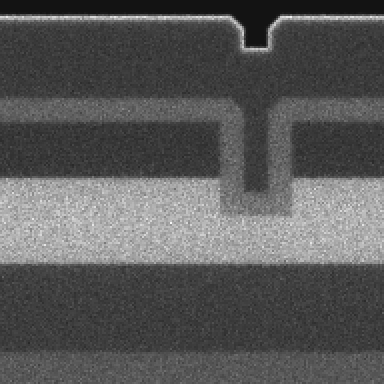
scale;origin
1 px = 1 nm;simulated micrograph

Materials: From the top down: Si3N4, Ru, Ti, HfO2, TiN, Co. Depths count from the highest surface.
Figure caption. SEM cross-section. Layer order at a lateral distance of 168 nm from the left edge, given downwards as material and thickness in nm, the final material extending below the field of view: Si3N4 82, Ru 24, Ti 56, HfO2 86, TiN 88, Co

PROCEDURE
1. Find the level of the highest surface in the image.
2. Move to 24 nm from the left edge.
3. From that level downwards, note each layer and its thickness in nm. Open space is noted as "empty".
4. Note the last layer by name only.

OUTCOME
Si3N4 82, Ru 24, Ti 56, HfO2 86, TiN 88, Co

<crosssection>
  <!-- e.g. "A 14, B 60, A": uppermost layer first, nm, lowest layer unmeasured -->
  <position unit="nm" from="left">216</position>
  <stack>Si3N4 82, Ru 24, Ti 56, HfO2 86, TiN 88, Co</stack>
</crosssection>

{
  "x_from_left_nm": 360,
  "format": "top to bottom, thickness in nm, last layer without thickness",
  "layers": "Si3N4 82, Ru 24, Ti 56, HfO2 86, TiN 88, Co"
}